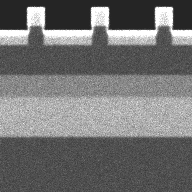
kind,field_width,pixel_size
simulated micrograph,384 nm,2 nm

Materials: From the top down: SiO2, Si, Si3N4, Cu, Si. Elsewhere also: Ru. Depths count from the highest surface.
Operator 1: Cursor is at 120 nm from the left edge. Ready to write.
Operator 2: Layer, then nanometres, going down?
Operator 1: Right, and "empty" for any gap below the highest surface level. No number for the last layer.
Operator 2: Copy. empty 46, SiO2 28, Si 60, Si3N4 44, Cu 80, Si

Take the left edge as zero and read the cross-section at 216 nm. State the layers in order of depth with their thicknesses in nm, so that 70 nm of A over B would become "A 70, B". empty 46, SiO2 28, Si 60, Si3N4 44, Cu 80, Si